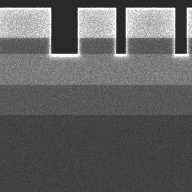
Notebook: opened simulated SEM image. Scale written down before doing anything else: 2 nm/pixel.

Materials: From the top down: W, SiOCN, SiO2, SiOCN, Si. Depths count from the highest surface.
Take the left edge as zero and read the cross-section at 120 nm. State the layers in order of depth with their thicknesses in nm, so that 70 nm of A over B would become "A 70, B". empty 92, SiO2 62, SiOCN 60, Si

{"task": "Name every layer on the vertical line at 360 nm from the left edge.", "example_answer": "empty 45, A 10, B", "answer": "empty 92, SiO2 62, SiOCN 60, Si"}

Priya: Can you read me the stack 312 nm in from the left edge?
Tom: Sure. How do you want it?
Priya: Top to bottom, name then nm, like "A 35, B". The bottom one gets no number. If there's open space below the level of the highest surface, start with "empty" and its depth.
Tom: W 60, SiOCN 32, SiO2 62, SiOCN 60, Si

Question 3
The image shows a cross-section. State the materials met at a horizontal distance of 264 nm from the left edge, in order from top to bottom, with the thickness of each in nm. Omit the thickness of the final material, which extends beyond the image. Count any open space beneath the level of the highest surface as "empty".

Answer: W 60, SiOCN 32, SiO2 62, SiOCN 60, Si